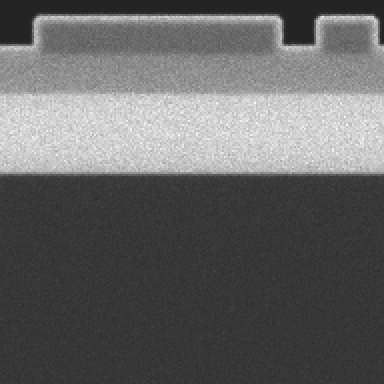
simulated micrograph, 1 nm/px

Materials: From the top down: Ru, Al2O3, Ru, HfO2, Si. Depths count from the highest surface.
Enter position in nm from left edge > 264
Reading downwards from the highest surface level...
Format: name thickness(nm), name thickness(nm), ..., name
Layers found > Ru 8, Al2O3 30, Ru 40, HfO2 80, Si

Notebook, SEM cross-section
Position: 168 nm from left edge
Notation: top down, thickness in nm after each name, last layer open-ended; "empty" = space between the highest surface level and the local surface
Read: Ru 8, Al2O3 30, Ru 40, HfO2 80, Si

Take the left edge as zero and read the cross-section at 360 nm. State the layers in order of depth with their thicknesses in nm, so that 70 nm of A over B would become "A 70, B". Ru 8, Al2O3 30, Ru 40, HfO2 80, Si